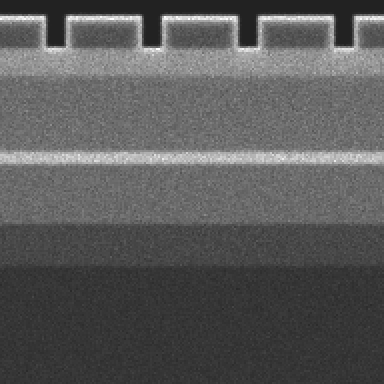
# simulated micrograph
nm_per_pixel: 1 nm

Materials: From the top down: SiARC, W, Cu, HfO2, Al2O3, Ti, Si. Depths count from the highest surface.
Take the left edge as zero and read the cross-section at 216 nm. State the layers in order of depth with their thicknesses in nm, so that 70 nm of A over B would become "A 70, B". SiARC 32, W 28, Cu 76, HfO2 12, Al2O3 60, Ti 42, Si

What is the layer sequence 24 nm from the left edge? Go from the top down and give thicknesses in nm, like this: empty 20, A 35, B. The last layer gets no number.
SiARC 32, W 28, Cu 76, HfO2 12, Al2O3 60, Ti 42, Si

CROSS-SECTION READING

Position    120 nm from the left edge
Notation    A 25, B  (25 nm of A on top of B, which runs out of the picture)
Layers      SiARC 32, W 28, Cu 76, HfO2 12, Al2O3 60, Ti 42, Si